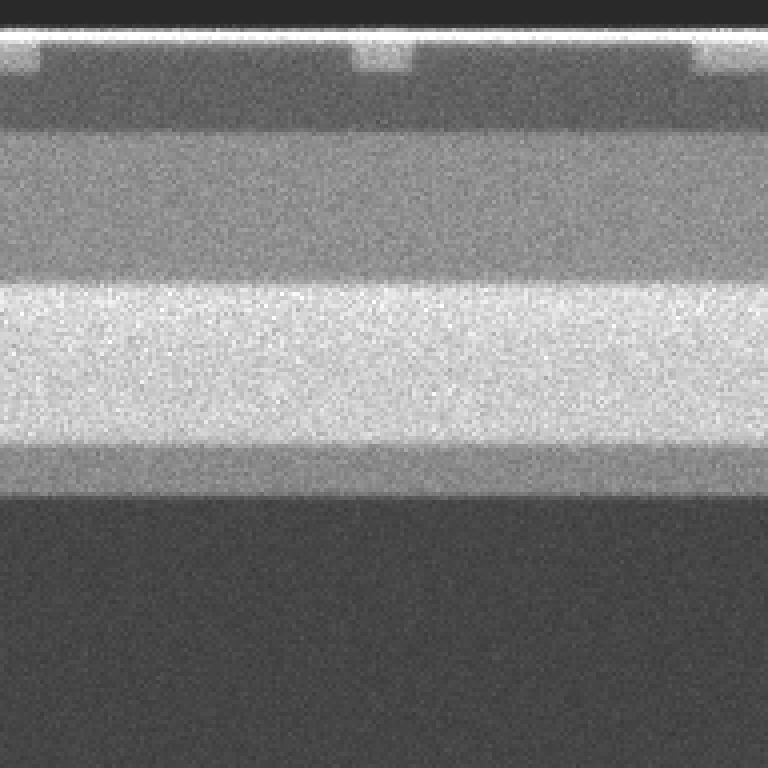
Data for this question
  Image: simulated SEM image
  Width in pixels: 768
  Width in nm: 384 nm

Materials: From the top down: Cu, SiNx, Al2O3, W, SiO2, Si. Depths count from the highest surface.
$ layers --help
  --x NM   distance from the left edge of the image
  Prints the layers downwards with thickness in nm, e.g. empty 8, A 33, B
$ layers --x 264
SiNx 50, Al2O3 76, W 80, SiO2 26, Si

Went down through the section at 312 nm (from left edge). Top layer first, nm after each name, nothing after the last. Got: SiNx 50, Al2O3 76, W 80, SiO2 26, Si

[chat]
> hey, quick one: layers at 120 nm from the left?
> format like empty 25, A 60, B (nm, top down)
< SiNx 50, Al2O3 76, W 80, SiO2 26, Si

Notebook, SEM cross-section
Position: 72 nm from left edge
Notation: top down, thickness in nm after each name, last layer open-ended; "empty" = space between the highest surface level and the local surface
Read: SiNx 50, Al2O3 76, W 80, SiO2 26, Si